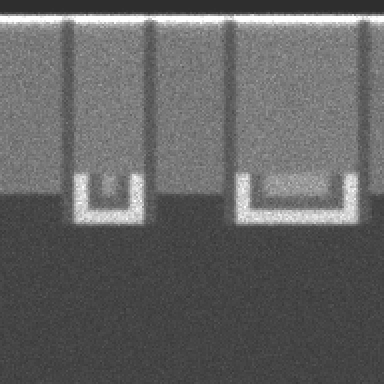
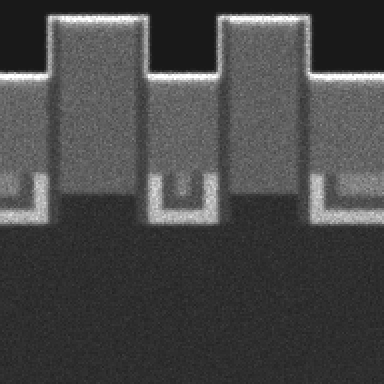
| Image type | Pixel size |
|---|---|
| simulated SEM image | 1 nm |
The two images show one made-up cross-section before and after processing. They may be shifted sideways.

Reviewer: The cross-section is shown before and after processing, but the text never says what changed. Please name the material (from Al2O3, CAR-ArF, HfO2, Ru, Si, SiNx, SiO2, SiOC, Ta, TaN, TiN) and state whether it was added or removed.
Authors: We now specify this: Al2O3, removed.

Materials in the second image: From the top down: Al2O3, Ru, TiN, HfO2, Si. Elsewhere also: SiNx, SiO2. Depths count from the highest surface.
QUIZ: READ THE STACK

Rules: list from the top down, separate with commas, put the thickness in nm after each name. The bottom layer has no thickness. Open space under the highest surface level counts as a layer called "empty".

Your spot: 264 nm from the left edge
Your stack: SiO2 178, Si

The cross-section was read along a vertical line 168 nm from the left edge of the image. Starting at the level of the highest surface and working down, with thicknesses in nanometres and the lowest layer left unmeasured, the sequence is empty 58, Al2O3 100, TiN 36, HfO2 14, Si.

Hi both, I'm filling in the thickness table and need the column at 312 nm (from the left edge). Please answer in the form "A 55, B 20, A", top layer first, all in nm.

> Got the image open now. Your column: empty 58, Al2O3 100, HfO2 50, Si